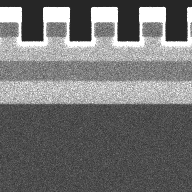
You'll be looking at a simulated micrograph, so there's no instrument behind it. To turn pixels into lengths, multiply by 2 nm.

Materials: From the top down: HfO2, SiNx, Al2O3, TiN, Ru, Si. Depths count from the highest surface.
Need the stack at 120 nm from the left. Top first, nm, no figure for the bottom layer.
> HfO2 28, SiNx 30, Al2O3 48, TiN 40, Ru 46, Si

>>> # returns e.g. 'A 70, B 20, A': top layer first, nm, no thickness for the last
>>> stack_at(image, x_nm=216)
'HfO2 28, SiNx 30, Al2O3 48, TiN 40, Ru 46, Si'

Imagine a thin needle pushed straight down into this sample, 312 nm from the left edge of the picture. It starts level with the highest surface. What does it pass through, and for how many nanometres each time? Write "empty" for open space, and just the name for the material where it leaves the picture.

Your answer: HfO2 28, SiNx 30, Al2O3 48, TiN 40, Ru 46, Si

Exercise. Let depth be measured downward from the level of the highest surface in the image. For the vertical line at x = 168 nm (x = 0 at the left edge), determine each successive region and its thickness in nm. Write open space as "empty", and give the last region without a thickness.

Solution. empty 68, Al2O3 38, TiN 40, Ru 46, Si